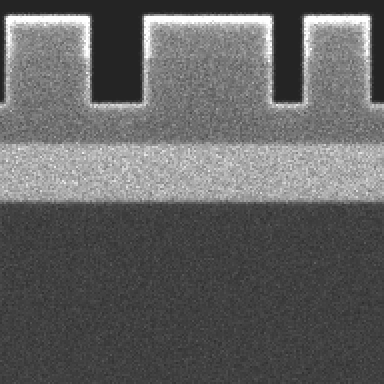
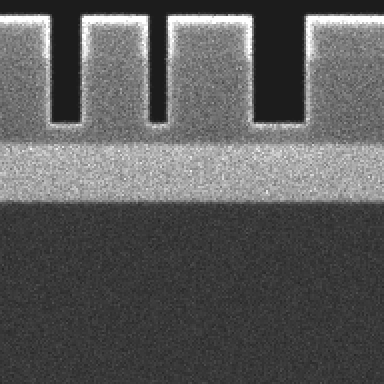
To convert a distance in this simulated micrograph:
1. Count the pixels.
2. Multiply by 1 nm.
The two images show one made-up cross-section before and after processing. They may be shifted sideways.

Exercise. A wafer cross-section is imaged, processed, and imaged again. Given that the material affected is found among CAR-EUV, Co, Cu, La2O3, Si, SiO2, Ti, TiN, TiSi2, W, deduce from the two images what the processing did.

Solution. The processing removed TiN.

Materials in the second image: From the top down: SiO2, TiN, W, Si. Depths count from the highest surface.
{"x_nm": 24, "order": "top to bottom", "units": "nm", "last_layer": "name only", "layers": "SiO2 42, TiN 86, W 58, Si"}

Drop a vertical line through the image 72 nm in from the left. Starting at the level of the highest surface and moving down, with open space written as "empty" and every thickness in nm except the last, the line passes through empty 108, TiN 20, W 58, Si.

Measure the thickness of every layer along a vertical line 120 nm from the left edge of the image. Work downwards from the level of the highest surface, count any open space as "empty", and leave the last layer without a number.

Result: SiO2 42, TiN 86, W 58, Si